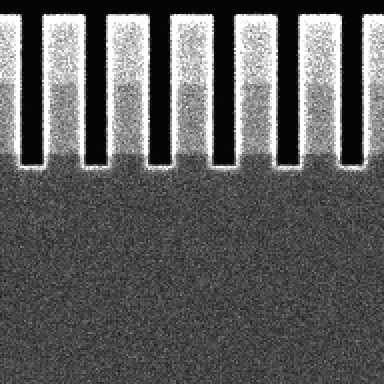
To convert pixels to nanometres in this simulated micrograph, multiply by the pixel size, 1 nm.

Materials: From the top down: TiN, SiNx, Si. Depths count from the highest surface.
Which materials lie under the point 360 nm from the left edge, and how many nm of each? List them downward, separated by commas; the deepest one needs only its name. empty 150, Si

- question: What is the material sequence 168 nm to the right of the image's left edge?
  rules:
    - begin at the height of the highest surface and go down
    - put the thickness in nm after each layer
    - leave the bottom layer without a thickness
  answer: empty 150, Si